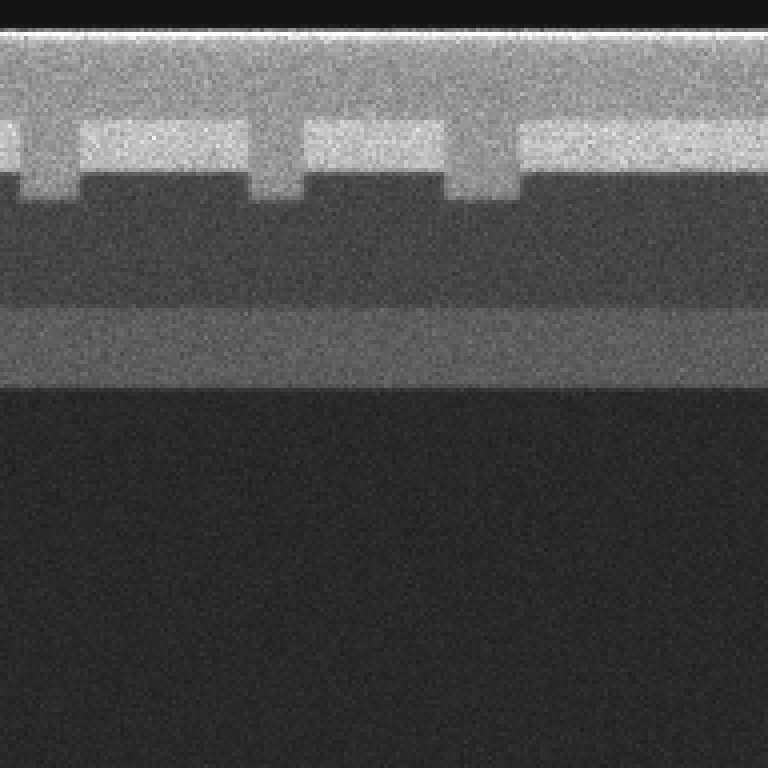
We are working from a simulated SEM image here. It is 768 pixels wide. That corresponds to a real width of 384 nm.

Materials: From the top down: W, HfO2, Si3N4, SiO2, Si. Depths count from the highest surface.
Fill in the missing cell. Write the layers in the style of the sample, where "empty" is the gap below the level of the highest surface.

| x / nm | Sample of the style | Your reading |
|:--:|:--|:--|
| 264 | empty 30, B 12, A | W 44, HfO2 26, Si3N4 68, SiO2 40, Si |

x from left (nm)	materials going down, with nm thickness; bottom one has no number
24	W 84, Si3N4 54, SiO2 40, Si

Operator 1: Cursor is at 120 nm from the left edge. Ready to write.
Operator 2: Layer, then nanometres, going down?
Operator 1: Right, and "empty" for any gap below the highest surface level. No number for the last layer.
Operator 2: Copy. W 44, HfO2 26, Si3N4 68, SiO2 40, Si